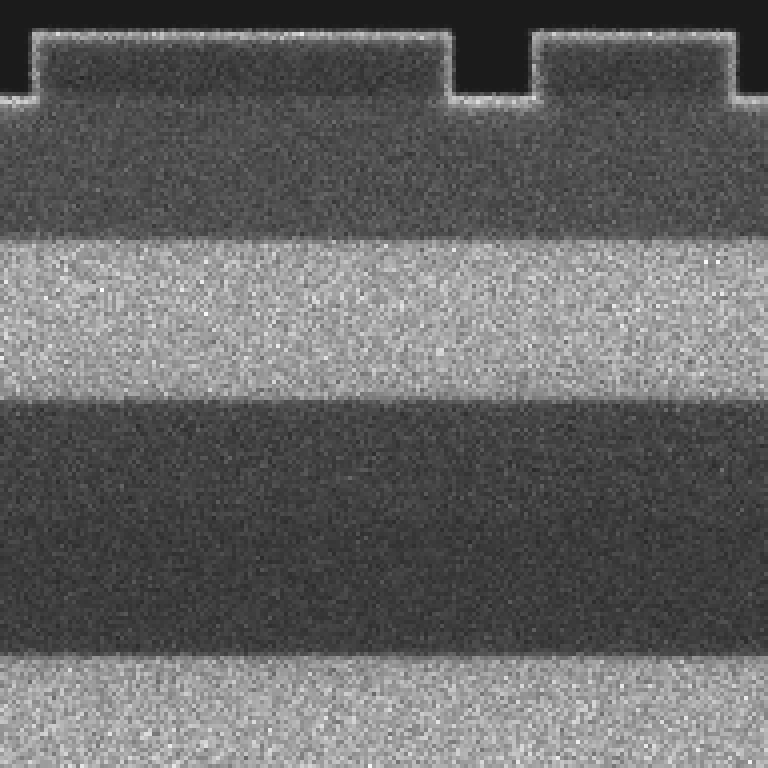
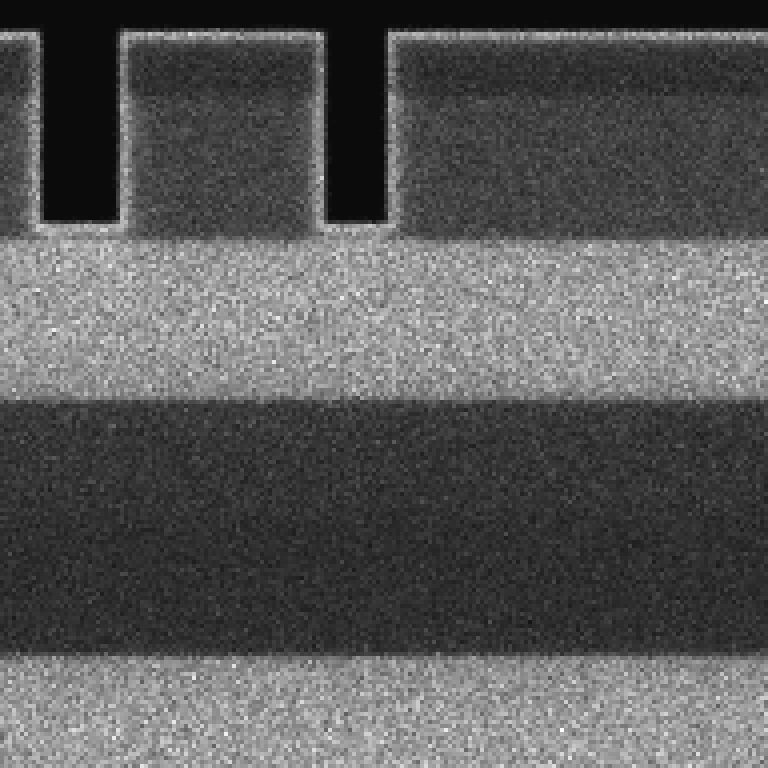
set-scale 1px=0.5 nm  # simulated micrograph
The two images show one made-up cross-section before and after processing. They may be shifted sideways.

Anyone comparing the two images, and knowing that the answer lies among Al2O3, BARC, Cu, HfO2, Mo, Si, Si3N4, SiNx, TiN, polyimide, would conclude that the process removed Al2O3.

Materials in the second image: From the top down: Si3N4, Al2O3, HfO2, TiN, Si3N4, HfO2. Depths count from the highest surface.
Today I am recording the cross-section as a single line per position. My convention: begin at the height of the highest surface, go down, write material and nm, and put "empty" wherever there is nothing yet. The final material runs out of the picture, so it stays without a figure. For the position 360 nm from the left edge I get Si3N4 32, Al2O3 72, HfO2 80, TiN 58, Si3N4 70, HfO2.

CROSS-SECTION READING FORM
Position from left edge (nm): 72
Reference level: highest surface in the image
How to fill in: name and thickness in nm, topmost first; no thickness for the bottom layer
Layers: Si3N4 32, Al2O3 72, HfO2 80, TiN 58, Si3N4 70, HfO2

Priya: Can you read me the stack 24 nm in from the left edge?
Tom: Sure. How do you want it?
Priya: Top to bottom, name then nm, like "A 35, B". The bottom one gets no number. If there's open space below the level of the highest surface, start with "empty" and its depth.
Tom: empty 96, Al2O3 8, HfO2 80, TiN 58, Si3N4 70, HfO2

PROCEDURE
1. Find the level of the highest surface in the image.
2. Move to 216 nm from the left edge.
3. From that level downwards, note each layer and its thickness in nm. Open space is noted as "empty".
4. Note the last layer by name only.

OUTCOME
Si3N4 32, Al2O3 72, HfO2 80, TiN 58, Si3N4 70, HfO2